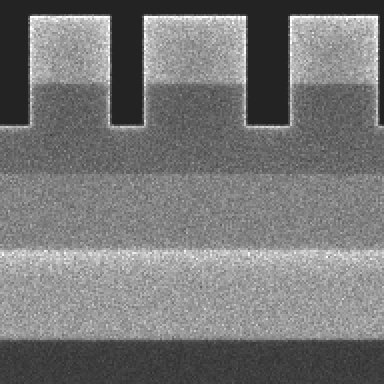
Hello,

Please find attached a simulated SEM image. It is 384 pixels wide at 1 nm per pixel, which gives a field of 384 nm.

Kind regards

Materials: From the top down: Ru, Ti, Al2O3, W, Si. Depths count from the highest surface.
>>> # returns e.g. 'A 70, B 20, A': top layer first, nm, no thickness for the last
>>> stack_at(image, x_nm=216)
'Ru 68, Ti 90, Al2O3 76, W 90, Si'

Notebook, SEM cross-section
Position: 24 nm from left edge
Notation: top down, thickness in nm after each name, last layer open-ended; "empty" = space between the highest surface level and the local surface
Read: empty 110, Ti 48, Al2O3 76, W 90, Si